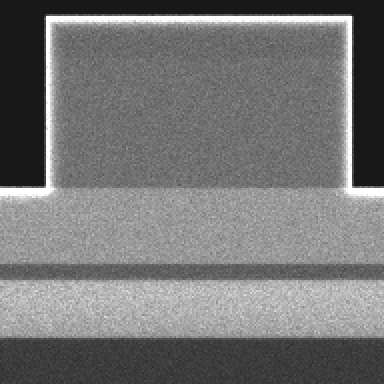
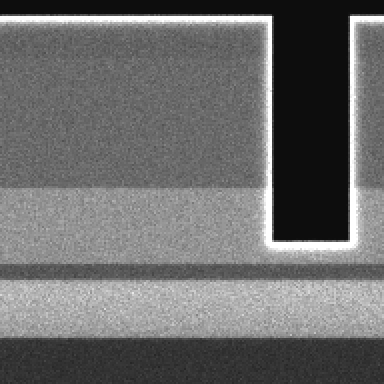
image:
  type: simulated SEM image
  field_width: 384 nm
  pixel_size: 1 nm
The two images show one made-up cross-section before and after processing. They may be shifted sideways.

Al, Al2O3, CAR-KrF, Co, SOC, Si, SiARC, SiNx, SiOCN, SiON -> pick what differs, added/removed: Al2O3 removed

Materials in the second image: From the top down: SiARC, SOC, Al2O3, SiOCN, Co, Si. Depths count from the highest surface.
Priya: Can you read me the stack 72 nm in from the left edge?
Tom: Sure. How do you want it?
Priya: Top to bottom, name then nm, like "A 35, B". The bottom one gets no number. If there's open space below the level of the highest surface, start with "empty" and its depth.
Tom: SiARC 42, SOC 130, Al2O3 76, SiOCN 16, Co 58, Si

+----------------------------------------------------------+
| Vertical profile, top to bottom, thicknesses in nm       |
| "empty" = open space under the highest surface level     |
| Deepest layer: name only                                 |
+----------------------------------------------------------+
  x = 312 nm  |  empty 226, Al2O3 22, SiOCN 16, Co 58, Si